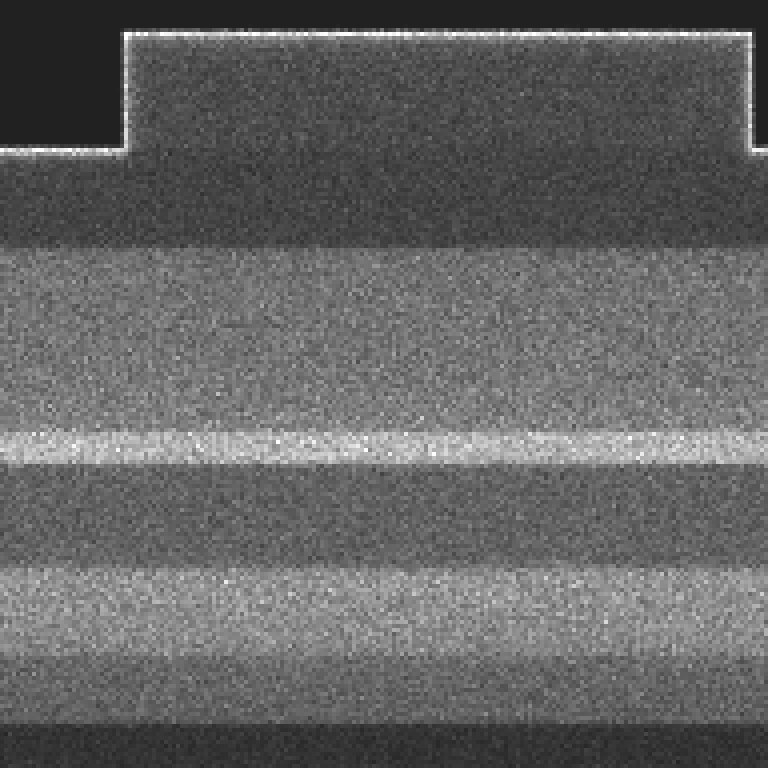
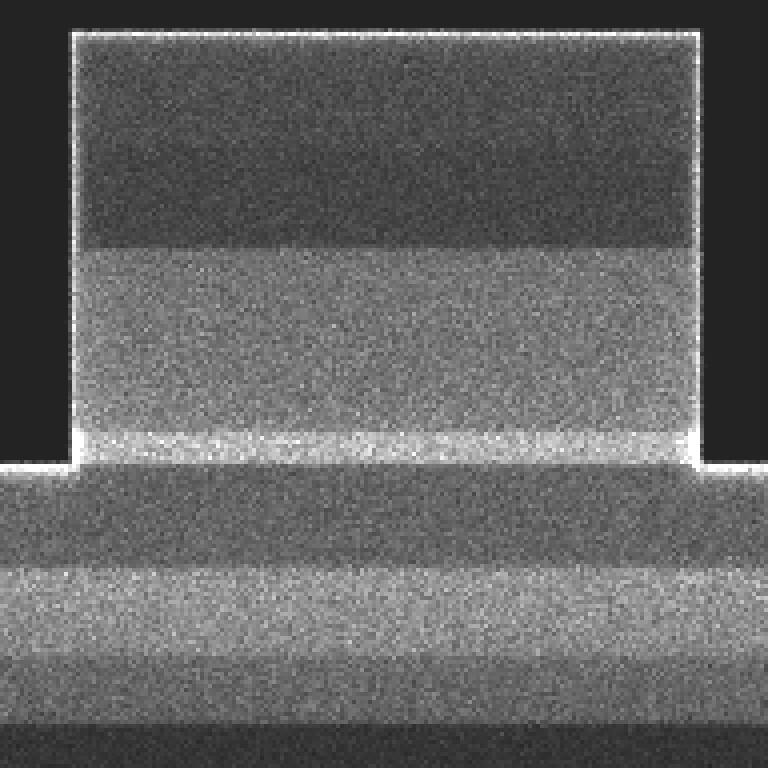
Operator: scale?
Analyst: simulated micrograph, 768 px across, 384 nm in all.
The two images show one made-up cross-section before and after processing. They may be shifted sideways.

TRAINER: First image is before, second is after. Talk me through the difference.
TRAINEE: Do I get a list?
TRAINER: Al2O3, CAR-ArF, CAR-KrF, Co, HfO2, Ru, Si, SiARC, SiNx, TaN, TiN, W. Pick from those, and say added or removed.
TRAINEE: removed: HfO2 and Ru and SiNx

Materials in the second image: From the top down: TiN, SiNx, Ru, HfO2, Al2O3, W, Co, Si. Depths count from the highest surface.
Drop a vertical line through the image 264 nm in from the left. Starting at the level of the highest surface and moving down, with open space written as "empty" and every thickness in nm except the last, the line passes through TiN 58, SiNx 50, Ru 92, HfO2 16, Al2O3 52, W 44, Co 34, Si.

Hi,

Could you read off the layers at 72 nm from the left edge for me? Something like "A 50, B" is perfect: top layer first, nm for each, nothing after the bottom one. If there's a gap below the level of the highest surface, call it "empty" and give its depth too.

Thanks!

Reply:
TiN 58, SiNx 50, Ru 92, HfO2 16, Al2O3 52, W 44, Co 34, Si